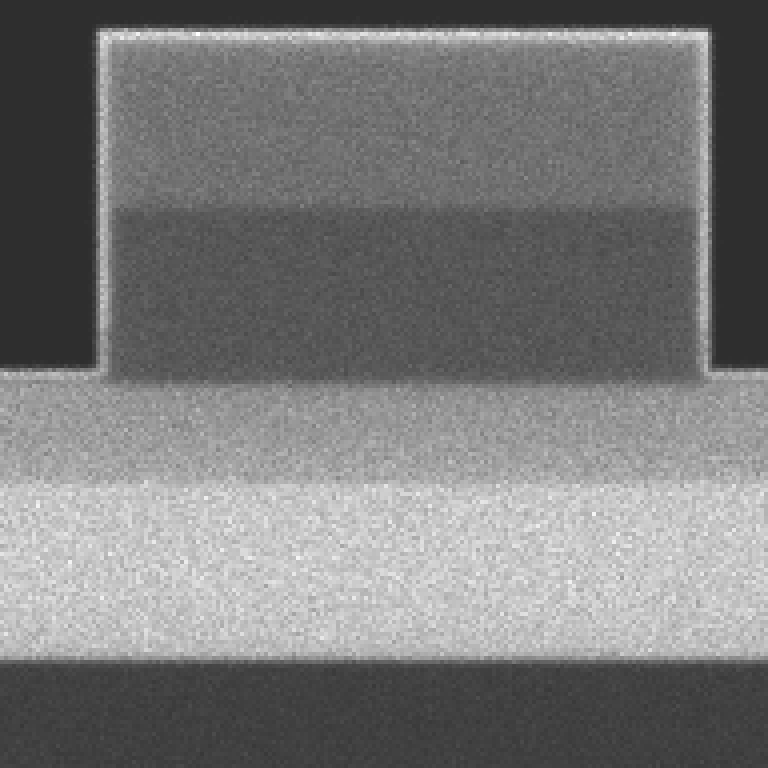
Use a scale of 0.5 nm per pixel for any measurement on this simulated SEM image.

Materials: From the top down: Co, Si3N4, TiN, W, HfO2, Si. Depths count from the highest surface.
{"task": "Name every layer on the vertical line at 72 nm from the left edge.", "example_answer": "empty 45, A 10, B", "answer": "Co 88, Si3N4 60, TiN 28, W 50, HfO2 88, Si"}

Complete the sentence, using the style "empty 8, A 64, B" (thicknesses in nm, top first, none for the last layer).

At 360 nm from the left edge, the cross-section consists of empty 170, TiN 6, W 50, HfO2 88, Si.